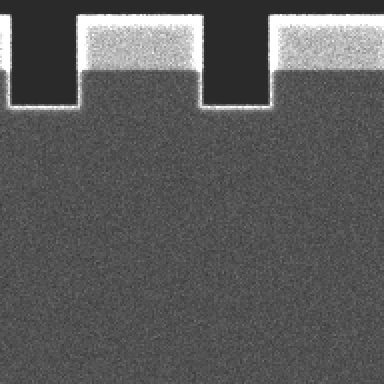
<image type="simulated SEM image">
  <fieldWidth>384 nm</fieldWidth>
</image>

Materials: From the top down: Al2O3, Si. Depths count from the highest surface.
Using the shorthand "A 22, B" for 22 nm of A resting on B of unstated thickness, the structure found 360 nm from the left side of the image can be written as Al2O3 54, Si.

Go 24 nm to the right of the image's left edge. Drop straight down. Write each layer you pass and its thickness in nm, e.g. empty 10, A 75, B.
empty 90, Si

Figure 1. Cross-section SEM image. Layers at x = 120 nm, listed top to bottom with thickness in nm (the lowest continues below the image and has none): Al2O3 54, Si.